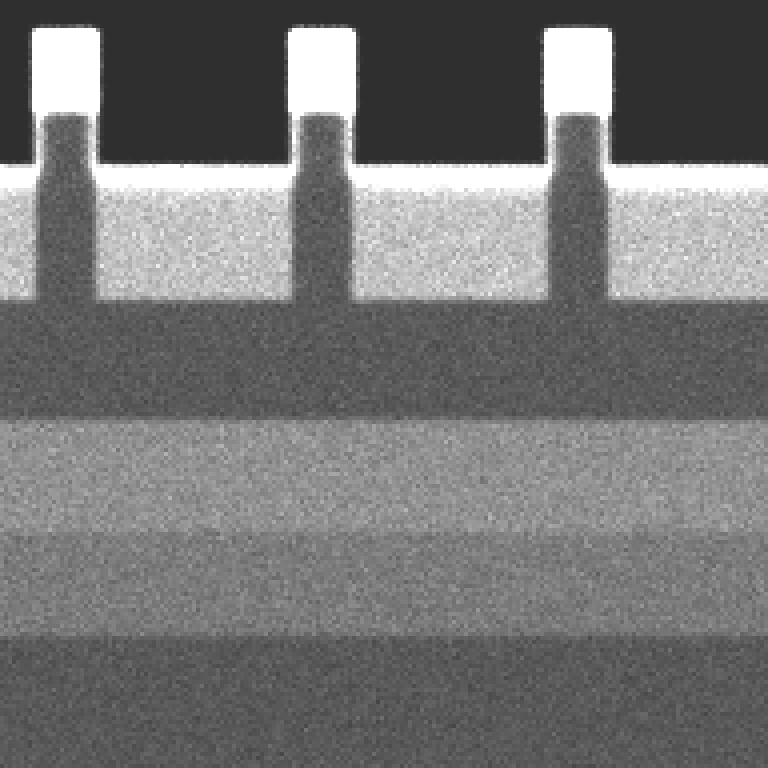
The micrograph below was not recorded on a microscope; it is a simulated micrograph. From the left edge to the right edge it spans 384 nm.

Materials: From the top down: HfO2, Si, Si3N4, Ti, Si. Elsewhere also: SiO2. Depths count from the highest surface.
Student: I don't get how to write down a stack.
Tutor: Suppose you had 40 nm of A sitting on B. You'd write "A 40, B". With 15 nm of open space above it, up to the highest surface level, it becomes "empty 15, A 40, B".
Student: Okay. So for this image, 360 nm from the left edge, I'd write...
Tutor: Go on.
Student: empty 68, SiO2 66, Si 60, Si3N4 56, Ti 52, Si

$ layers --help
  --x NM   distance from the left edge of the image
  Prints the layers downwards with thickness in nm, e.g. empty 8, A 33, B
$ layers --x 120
empty 68, SiO2 66, Si 60, Si3N4 56, Ti 52, Si